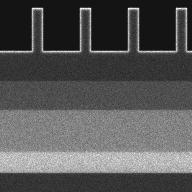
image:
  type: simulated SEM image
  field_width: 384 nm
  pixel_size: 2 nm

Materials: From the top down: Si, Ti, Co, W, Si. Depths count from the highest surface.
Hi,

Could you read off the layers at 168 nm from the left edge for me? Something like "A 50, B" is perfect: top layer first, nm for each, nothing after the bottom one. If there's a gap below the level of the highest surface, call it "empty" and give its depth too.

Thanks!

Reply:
Si 146, Ti 58, Co 84, W 42, Si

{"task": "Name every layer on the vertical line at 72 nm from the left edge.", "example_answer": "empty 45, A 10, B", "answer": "Si 146, Ti 58, Co 84, W 42, Si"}